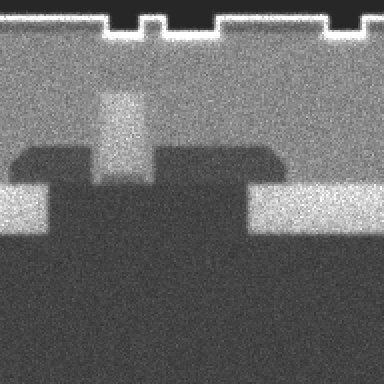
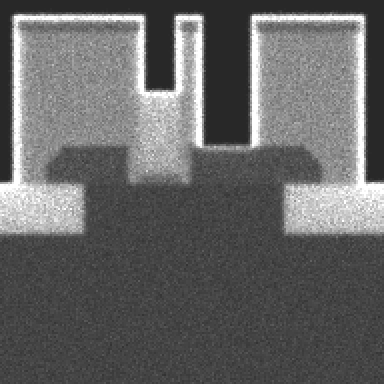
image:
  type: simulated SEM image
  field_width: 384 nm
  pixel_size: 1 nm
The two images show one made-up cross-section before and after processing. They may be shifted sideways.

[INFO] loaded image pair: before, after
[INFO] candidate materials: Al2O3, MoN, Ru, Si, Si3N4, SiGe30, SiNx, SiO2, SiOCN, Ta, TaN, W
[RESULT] removed SiO2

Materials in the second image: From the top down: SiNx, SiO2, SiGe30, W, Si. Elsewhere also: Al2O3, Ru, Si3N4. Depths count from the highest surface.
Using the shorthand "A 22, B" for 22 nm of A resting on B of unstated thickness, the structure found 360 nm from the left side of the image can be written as SiNx 16, SiO2 152, W 50, Si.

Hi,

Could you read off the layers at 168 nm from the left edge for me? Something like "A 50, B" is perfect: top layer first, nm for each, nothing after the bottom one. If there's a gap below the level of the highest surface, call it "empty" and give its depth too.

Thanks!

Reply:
empty 76, Ru 82, Si3N4 10, Si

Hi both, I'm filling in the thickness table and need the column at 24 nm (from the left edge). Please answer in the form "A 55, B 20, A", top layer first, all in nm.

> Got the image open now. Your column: SiNx 16, SiO2 152, W 50, Si